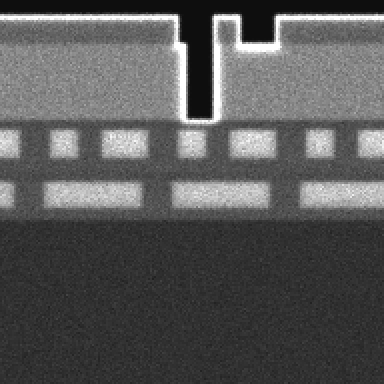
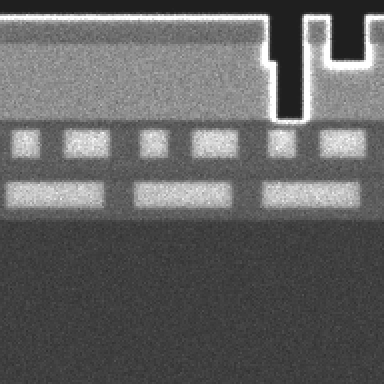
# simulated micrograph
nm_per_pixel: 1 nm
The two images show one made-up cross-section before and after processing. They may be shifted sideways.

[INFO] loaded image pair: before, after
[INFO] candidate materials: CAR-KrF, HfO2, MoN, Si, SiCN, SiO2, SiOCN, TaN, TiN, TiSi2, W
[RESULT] removed SiO2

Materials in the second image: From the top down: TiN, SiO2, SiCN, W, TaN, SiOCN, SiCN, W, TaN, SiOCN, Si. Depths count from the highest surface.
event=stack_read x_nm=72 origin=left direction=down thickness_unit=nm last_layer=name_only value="TiN 28, SiO2 76, SiCN 10, W 22, TaN 6, SiOCN 14, SiCN 10, W 20, TaN 6, SiOCN 12, Si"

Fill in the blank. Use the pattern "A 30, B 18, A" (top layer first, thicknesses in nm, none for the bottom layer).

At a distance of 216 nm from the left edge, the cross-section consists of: TiN 28, SiO2 76, SiCN 10, W 22, TaN 6, SiOCN 14, SiCN 10, W 20, TaN 6, SiOCN 12, Si